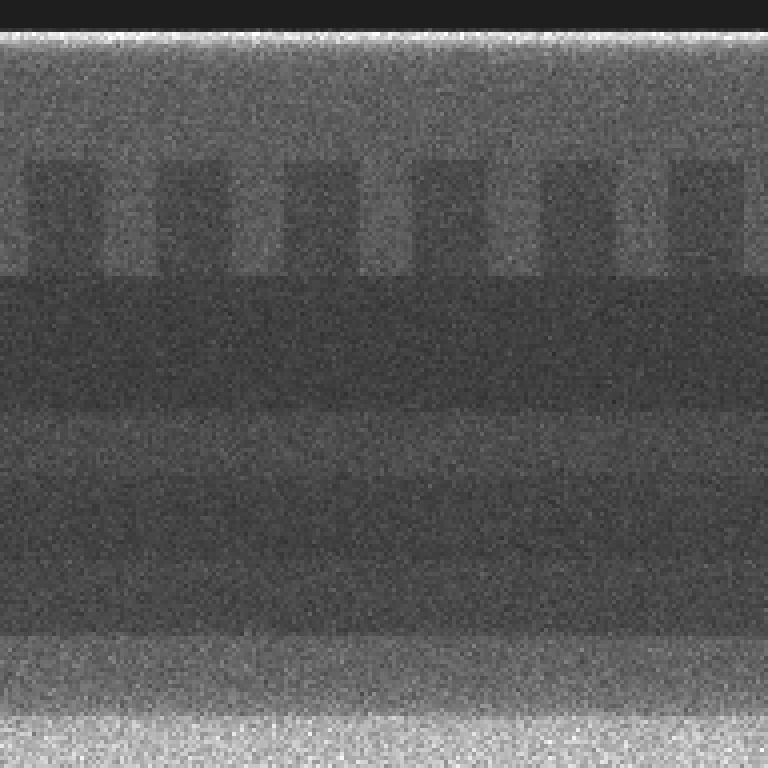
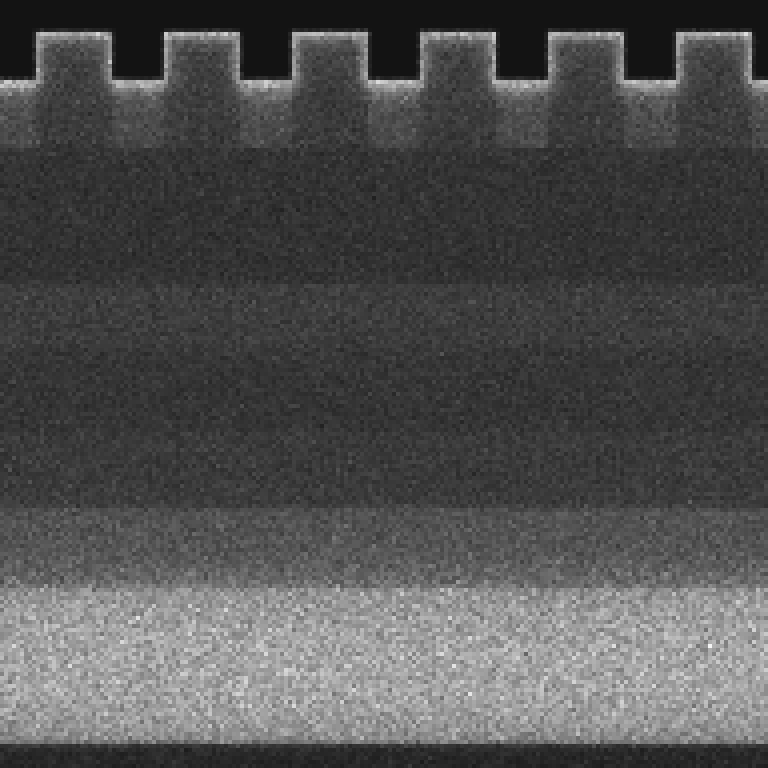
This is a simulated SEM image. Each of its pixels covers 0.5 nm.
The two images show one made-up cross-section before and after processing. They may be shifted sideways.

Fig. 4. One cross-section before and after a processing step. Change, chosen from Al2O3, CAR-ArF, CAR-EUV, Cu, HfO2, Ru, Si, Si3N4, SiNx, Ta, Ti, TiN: Al2O3 removed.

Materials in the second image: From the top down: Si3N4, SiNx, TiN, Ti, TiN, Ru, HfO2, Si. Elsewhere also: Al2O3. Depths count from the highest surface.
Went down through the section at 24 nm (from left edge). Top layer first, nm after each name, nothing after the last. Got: Si3N4 58, SiNx 68, TiN 32, Ti 42, TiN 38, Ru 40, HfO2 78, Si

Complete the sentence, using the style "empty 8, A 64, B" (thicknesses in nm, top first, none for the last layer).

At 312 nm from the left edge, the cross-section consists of empty 24, Al2O3 34, SiNx 68, TiN 32, Ti 42, TiN 38, Ru 40, HfO2 78, Si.